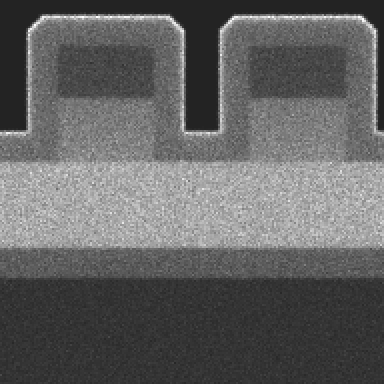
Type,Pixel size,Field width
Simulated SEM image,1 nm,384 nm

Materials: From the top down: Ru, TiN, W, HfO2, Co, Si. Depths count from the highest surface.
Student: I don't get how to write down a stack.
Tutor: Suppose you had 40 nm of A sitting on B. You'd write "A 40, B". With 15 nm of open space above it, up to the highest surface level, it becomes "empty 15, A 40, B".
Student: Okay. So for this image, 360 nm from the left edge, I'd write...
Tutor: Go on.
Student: Ru 146, HfO2 86, Co 30, Si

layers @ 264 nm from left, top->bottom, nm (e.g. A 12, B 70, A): Ru 30, TiN 52, W 64, HfO2 86, Co 30, Si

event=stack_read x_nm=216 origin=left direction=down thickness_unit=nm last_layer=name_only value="empty 116, Ru 30, HfO2 86, Co 30, Si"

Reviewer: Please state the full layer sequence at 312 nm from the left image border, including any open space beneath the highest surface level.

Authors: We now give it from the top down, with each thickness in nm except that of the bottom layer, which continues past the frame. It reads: Ru 30, TiN 52, W 64, HfO2 86, Co 30, Si